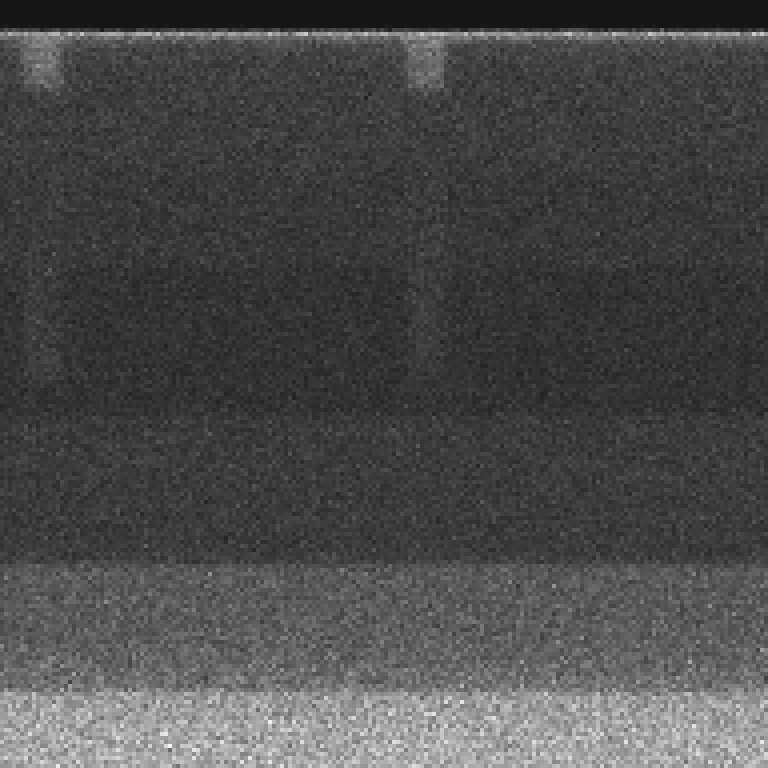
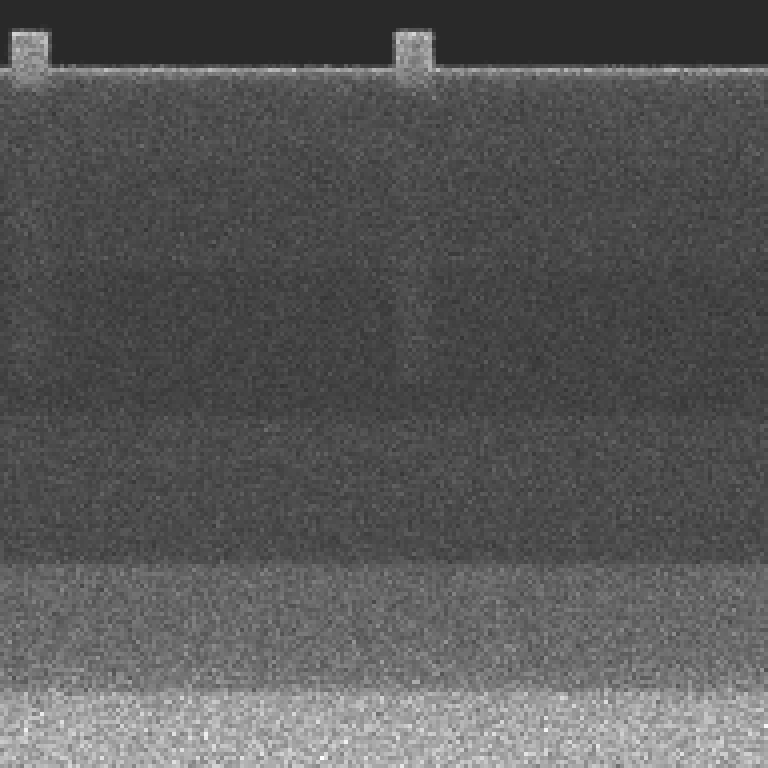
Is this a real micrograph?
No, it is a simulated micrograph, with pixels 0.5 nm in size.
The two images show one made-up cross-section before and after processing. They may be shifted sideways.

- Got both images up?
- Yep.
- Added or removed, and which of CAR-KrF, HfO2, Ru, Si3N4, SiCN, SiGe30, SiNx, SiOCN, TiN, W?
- removed, TiN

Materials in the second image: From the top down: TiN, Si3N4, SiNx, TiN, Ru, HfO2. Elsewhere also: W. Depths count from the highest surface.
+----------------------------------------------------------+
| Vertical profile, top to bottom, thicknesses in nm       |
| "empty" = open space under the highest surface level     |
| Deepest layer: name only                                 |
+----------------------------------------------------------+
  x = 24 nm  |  empty 18, TiN 50, Si3N4 50, SiNx 74, TiN 74, Ru 64, HfO2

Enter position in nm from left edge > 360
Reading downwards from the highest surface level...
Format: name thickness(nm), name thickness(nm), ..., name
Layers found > empty 18, TiN 50, Si3N4 50, SiNx 74, TiN 74, Ru 64, HfO2